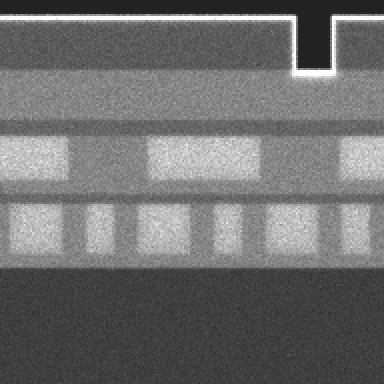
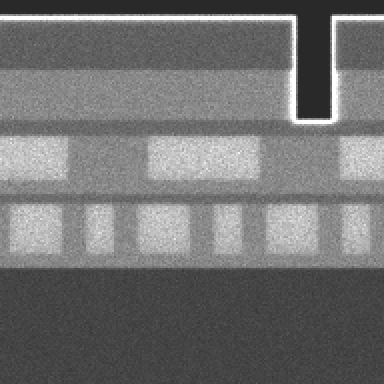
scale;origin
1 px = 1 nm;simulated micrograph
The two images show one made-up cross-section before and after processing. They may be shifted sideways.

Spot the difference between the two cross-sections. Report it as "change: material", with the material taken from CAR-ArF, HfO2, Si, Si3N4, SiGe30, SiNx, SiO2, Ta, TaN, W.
removed: SiO2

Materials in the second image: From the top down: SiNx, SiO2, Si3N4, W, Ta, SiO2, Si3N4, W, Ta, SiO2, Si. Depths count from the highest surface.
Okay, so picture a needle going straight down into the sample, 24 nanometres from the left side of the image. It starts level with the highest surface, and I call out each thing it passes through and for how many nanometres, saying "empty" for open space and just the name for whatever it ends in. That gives SiNx 54, SiO2 50, Si3N4 16, W 34, Ta 10, SiO2 14, Si3N4 10, W 40, Ta 10, SiO2 14, Si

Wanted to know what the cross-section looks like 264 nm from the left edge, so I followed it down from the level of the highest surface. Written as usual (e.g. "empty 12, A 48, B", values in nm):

SiNx 54, SiO2 50, Si3N4 16, SiO2 58, Si3N4 10, SiO2 64, Si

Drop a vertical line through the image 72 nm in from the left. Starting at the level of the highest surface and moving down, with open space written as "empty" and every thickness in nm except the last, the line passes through SiNx 54, SiO2 50, Si3N4 16, SiO2 58, Si3N4 10, SiO2 64, Si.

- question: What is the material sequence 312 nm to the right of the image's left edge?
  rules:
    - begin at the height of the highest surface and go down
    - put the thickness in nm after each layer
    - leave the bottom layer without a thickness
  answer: empty 104, Si3N4 16, SiO2 58, Si3N4 10, Ta 50, SiO2 14, Si